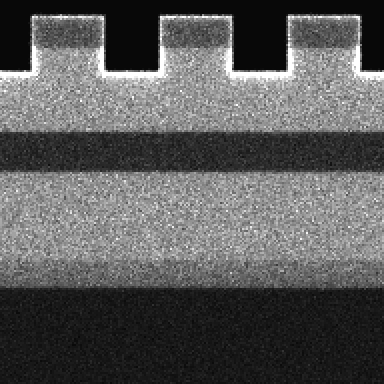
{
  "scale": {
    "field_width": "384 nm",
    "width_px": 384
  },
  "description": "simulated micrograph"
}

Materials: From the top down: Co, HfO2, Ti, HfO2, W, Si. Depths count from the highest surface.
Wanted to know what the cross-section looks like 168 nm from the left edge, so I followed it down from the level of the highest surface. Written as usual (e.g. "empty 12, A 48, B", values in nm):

Co 32, HfO2 84, Ti 40, HfO2 88, W 28, Si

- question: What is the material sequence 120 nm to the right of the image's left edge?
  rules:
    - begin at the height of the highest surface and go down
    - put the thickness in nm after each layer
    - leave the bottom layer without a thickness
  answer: empty 56, HfO2 60, Ti 40, HfO2 88, W 28, Si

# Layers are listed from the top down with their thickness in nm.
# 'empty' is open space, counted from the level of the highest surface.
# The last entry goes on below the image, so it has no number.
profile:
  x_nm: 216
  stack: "Co 32, HfO2 84, Ti 40, HfO2 88, W 28, Si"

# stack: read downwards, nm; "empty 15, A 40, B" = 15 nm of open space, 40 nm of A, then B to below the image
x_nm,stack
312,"Co 32, HfO2 84, Ti 40, HfO2 88, W 28, Si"